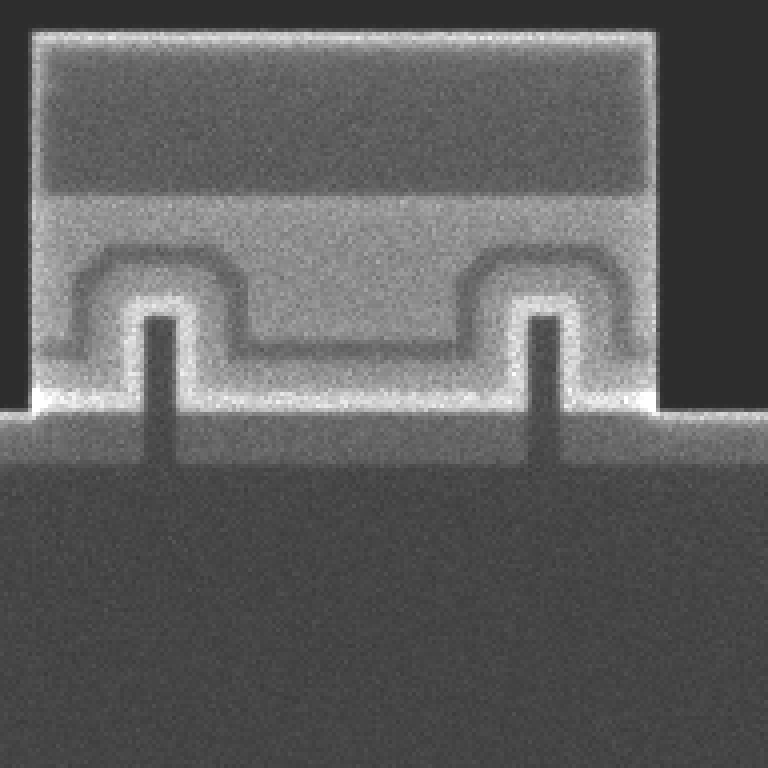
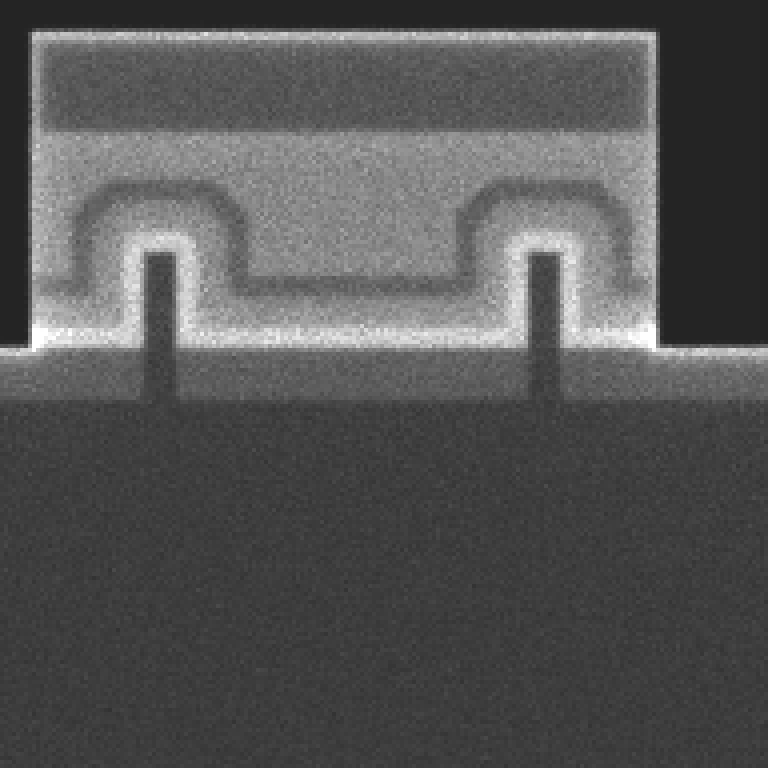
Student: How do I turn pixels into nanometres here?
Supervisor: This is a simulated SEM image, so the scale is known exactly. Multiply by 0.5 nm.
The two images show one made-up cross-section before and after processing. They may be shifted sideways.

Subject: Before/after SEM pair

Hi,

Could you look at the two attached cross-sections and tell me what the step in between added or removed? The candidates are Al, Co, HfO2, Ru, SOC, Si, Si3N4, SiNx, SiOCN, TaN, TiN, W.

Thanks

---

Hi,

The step removed SOC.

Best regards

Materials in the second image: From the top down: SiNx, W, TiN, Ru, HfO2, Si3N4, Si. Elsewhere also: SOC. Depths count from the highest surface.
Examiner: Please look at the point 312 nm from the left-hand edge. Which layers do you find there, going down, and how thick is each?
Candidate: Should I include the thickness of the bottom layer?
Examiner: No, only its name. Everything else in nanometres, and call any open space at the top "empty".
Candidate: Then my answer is SiNx 50, W 38, TiN 44, Ru 16, HfO2 10, Si3N4 26, Si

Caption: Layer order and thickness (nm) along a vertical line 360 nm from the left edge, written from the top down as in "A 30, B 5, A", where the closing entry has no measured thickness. empty 158, Si3N4 26, Si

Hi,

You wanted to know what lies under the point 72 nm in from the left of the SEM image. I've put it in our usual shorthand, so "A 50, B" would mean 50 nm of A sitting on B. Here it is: SiNx 50, W 24, TiN 10, Ru 16, HfO2 10, Si